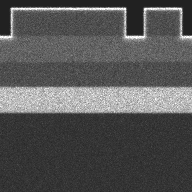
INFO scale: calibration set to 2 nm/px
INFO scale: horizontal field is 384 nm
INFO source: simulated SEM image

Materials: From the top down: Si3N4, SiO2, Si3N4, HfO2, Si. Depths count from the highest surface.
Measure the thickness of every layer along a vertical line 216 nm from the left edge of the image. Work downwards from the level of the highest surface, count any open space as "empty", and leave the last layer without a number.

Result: Si3N4 56, SiO2 52, Si3N4 50, HfO2 52, Si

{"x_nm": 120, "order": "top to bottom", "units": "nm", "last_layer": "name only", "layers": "Si3N4 56, SiO2 52, Si3N4 50, HfO2 52, Si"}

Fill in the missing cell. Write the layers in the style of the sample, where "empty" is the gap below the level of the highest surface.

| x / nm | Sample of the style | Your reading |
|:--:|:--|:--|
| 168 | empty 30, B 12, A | Si3N4 56, SiO2 52, Si3N4 50, HfO2 52, Si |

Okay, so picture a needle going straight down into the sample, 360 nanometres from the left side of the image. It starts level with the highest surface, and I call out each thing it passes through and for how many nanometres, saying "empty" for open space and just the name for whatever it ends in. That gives Si3N4 56, SiO2 52, Si3N4 50, HfO2 52, Si